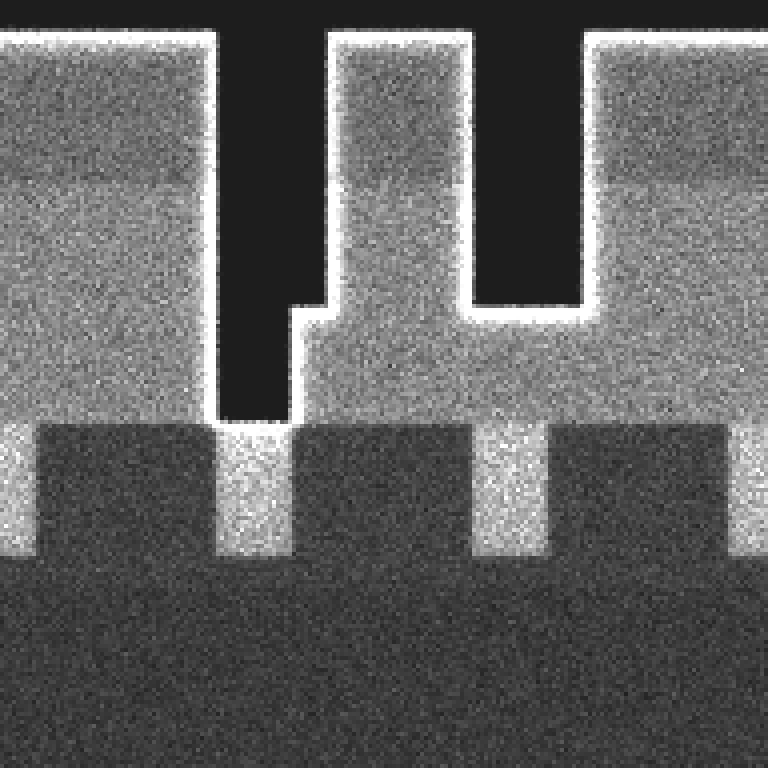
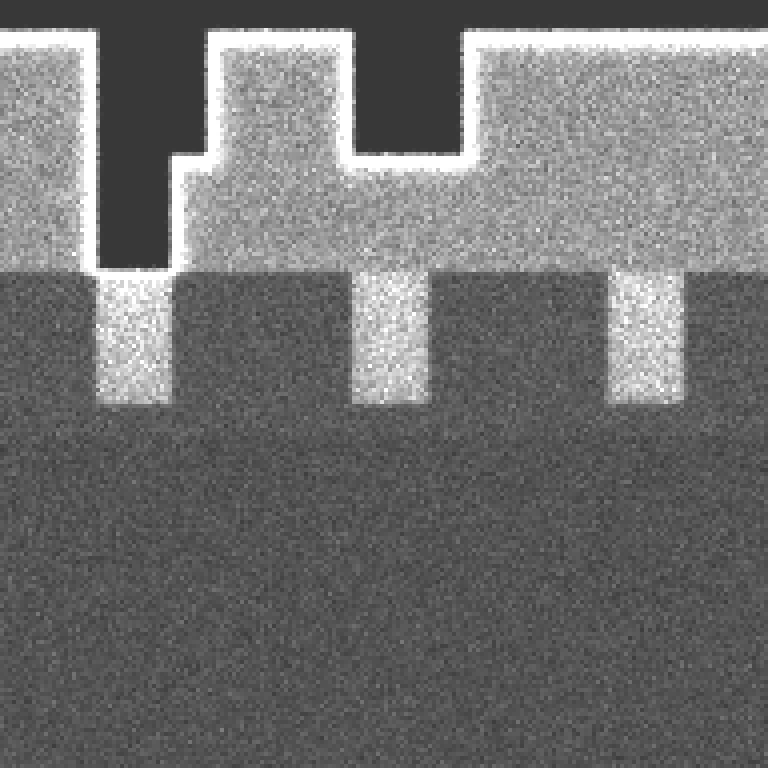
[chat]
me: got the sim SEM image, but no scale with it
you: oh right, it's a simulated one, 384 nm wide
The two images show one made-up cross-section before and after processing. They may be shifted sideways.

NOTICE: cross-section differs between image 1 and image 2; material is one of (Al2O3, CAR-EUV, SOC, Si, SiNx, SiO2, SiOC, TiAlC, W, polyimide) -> removed: SOC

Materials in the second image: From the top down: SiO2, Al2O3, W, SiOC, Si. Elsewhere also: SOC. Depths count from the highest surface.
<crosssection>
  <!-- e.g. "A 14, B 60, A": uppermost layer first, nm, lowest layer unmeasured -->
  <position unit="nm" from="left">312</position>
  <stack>SiO2 110, Al2O3 10, W 66, SiOC 16, Si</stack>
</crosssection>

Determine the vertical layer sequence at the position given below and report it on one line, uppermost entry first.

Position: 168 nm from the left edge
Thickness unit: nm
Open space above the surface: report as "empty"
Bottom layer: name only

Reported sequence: SiO2 110, Al2O3 10, SiOC 82, Si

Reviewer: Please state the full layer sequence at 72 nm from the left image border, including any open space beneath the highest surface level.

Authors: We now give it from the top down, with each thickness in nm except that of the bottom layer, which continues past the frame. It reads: empty 120, W 66, SiOC 16, Si